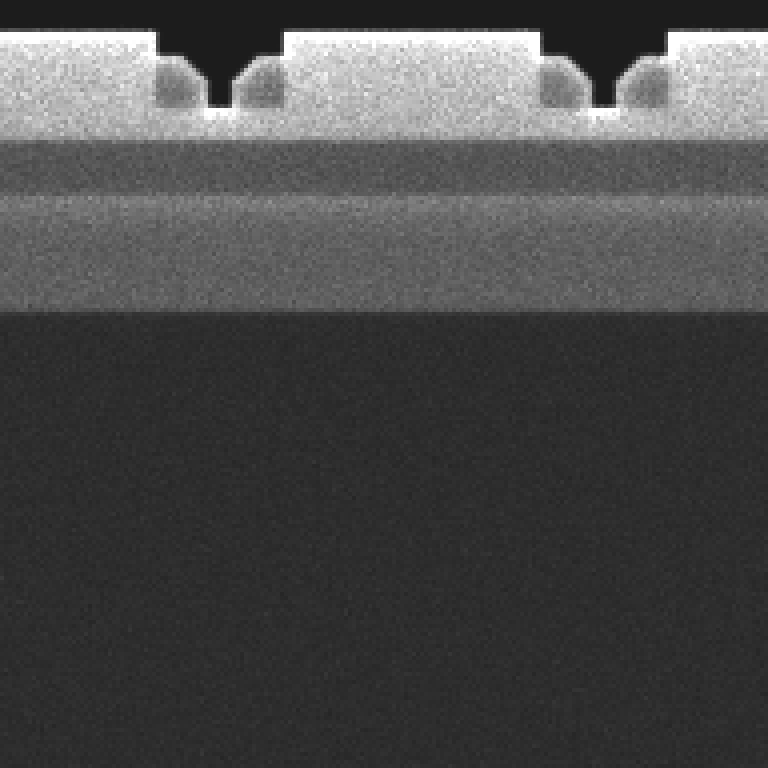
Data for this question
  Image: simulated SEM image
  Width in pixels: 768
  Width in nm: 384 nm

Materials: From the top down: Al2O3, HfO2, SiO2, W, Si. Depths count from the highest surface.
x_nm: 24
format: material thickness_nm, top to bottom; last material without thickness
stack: HfO2 54, SiO2 28, W 58, Si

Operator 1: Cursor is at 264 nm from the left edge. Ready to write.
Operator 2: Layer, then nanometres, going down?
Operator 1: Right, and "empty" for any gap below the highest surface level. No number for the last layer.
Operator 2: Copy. HfO2 54, SiO2 28, W 58, Si